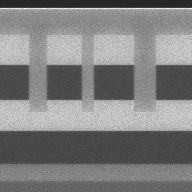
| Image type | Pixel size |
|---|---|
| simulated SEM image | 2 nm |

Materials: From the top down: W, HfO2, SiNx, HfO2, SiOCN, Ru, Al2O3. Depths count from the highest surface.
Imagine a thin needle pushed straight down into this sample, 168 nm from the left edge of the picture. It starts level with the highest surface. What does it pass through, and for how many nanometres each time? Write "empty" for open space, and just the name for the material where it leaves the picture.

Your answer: W 208, HfO2 38, SiOCN 66, Ru 34, Al2O3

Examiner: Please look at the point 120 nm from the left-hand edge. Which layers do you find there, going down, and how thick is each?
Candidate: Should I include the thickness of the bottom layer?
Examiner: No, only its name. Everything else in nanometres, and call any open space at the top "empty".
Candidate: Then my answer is W 54, HfO2 60, SiNx 70, HfO2 62, SiOCN 66, Ru 34, Al2O3